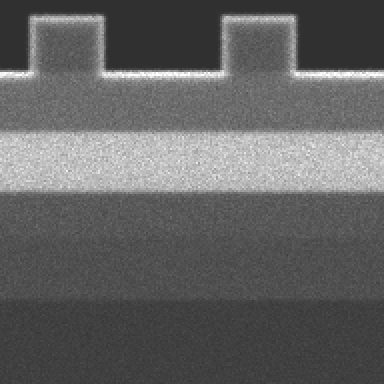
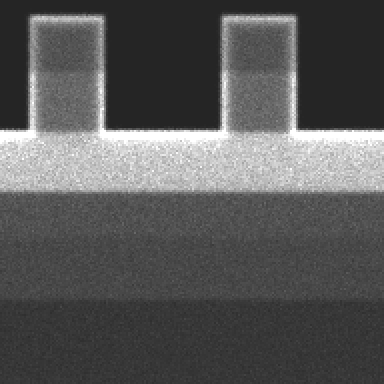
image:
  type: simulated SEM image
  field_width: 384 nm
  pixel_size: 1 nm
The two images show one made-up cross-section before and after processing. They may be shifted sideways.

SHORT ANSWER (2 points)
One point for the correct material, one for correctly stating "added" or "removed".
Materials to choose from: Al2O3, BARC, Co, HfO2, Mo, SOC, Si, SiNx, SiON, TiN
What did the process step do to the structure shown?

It removed Al2O3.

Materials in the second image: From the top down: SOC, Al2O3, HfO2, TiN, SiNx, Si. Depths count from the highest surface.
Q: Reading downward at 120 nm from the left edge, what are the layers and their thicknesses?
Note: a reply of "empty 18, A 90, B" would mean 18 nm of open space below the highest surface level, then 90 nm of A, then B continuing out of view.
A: empty 116, HfO2 60, TiN 46, SiNx 62, Si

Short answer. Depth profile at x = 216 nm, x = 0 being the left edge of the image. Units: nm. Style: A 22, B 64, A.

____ empty 116, HfO2 60, TiN 46, SiNx 62, Si